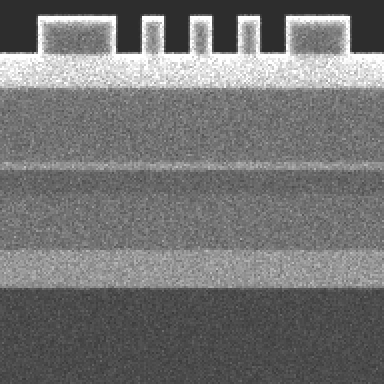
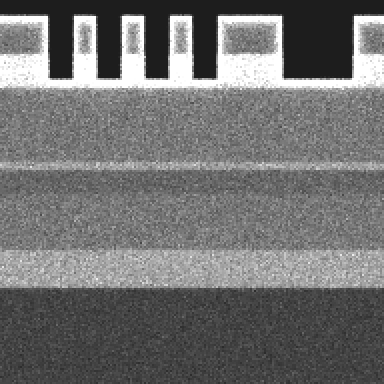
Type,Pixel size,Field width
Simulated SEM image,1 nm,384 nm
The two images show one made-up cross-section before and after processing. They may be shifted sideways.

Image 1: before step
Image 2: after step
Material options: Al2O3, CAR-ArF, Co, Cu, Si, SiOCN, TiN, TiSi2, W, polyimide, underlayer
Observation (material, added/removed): W, removed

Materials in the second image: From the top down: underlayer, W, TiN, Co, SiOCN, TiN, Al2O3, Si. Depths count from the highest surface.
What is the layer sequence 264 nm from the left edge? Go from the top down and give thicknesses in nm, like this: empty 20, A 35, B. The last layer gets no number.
underlayer 38, W 34, TiN 74, Co 8, SiOCN 24, TiN 56, Al2O3 38, Si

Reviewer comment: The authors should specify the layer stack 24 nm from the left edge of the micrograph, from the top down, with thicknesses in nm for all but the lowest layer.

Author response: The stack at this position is underlayer 38, W 34, TiN 74, Co 8, SiOCN 24, TiN 56, Al2O3 38, Si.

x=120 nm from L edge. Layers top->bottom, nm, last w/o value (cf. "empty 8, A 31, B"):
empty 64, W 8, TiN 74, Co 8, SiOCN 24, TiN 56, Al2O3 38, Si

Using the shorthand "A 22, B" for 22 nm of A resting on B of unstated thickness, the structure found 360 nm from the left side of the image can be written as underlayer 38, W 34, TiN 74, Co 8, SiOCN 24, TiN 56, Al2O3 38, Si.